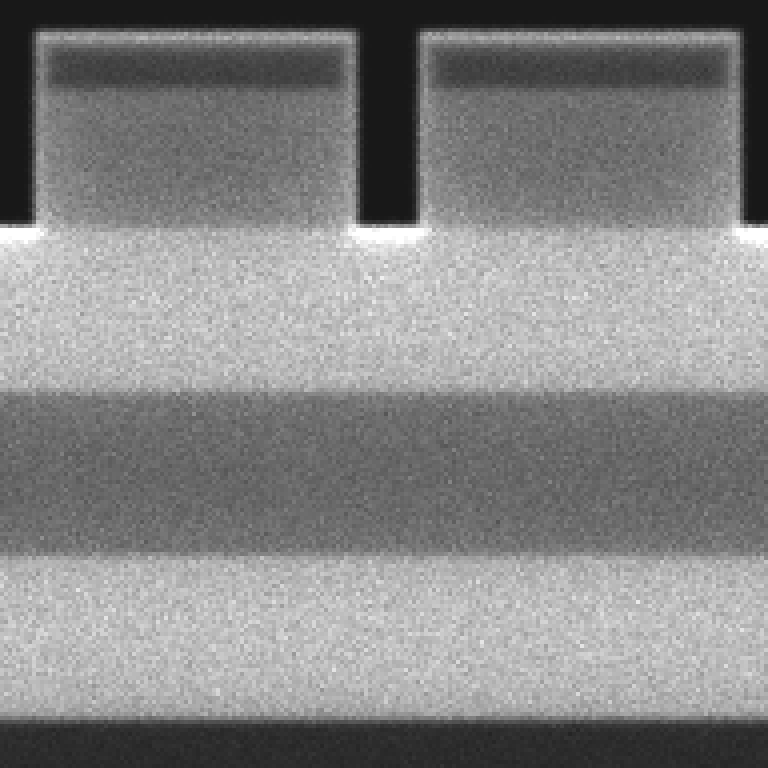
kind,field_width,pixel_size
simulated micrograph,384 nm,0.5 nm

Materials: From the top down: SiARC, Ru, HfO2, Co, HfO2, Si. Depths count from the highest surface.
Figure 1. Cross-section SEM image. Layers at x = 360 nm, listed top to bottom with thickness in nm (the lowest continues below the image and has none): SiARC 28, Ru 70, HfO2 82, Co 82, HfO2 82, Si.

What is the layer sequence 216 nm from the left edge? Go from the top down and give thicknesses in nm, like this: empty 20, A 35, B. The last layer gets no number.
SiARC 28, Ru 70, HfO2 82, Co 82, HfO2 82, Si